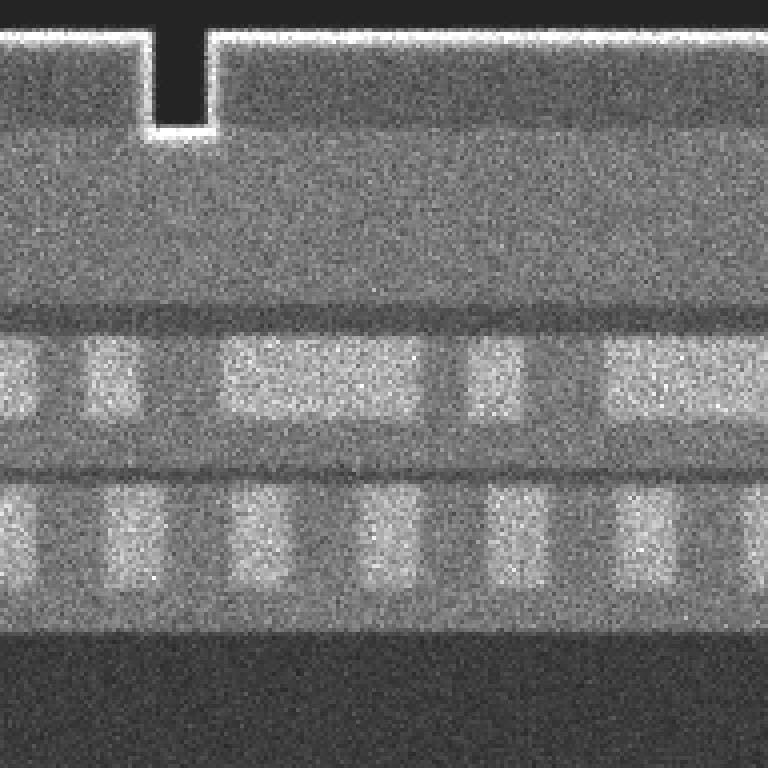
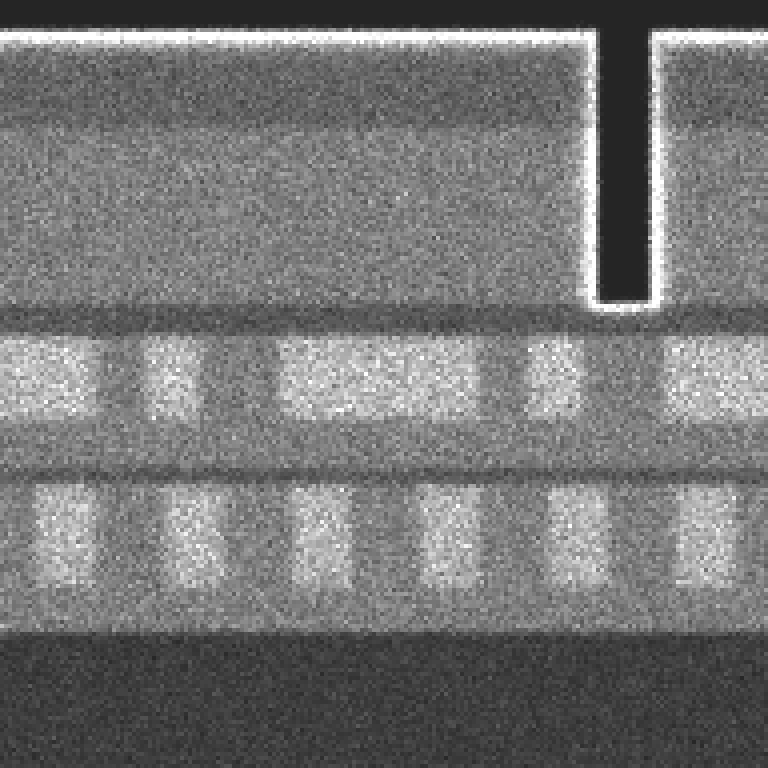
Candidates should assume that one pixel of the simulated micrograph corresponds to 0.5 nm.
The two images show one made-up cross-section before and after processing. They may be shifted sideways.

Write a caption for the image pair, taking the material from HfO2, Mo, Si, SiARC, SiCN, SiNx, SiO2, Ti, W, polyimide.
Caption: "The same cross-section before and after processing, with SiO2 removed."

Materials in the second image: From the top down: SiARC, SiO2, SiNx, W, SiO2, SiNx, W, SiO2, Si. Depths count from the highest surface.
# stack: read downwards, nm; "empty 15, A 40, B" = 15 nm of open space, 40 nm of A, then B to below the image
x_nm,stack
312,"empty 136, SiNx 16, SiO2 66, SiNx 8, SiO2 74, Si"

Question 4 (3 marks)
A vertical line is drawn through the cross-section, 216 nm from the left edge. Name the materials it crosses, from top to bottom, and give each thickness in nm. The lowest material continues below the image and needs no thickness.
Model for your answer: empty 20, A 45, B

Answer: SiARC 48, SiO2 88, SiNx 16, W 42, SiO2 24, SiNx 8, W 52, SiO2 22, Si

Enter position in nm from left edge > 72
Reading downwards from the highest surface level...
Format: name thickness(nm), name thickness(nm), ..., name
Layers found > SiARC 48, SiO2 88, SiNx 16, W 42, SiO2 24, SiNx 8, SiO2 74, Si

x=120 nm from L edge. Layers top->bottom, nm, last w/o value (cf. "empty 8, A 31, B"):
SiARC 48, SiO2 88, SiNx 16, SiO2 66, SiNx 8, SiO2 74, Si